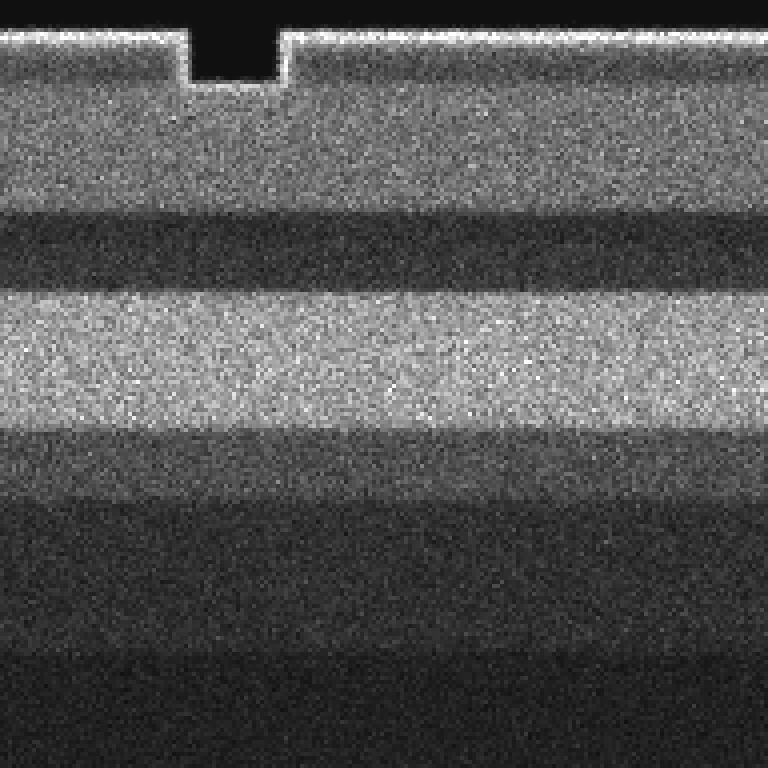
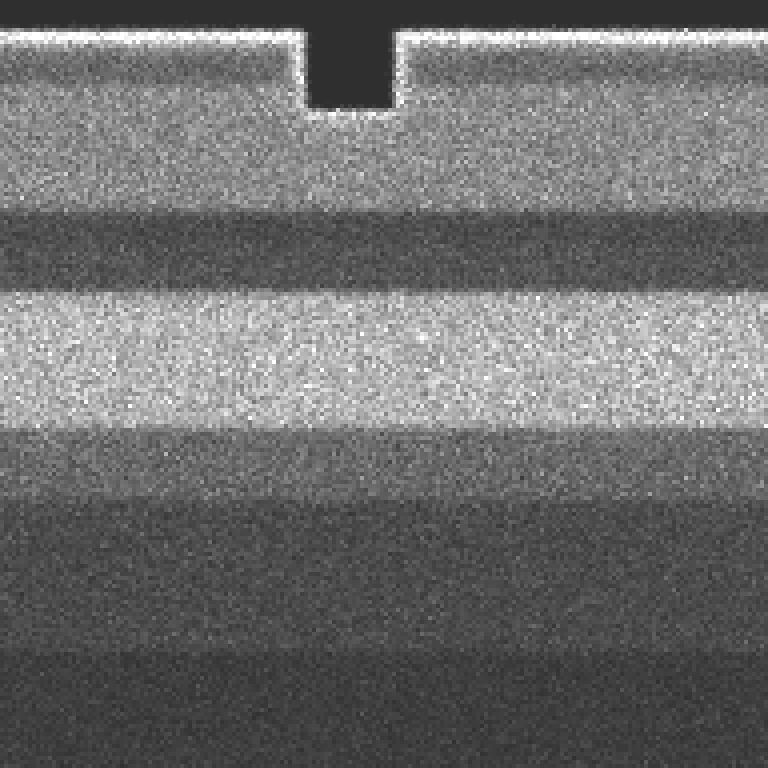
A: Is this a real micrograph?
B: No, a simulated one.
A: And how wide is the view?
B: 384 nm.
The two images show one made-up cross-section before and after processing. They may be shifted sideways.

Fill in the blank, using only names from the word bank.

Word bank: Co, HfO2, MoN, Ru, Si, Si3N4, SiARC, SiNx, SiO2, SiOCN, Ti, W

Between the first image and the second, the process removed W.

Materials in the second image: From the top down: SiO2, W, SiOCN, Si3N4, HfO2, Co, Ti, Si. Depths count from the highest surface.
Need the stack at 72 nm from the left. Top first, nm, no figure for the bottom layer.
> SiO2 26, W 64, SiOCN 16, Si3N4 24, HfO2 68, Co 36, Ti 76, Si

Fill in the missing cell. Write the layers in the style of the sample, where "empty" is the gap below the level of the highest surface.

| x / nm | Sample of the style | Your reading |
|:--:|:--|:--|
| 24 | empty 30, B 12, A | SiO2 26, W 64, SiOCN 16, Si3N4 24, HfO2 68, Co 36, Ti 76, Si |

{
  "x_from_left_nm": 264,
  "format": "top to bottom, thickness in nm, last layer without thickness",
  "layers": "SiO2 26, W 64, SiOCN 16, Si3N4 24, HfO2 68, Co 36, Ti 76, Si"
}